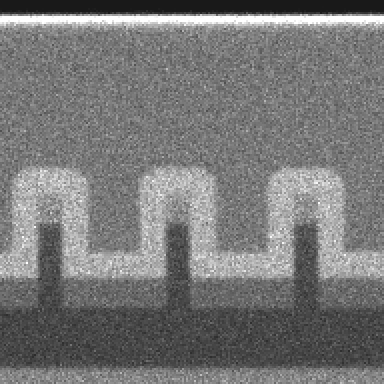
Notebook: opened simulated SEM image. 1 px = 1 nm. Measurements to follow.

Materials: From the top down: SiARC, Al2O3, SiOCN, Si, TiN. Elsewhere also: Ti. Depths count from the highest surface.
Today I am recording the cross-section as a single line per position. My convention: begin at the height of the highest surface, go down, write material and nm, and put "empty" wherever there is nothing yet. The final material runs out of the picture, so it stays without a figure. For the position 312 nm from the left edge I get SiARC 152, Al2O3 26, Ti 30, Si 144, TiN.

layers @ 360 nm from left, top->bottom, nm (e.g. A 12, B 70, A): SiARC 236, Al2O3 26, SiOCN 30, Si 60, TiN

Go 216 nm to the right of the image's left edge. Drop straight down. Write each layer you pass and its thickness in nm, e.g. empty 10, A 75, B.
SiARC 236, Al2O3 26, SiOCN 30, Si 60, TiN